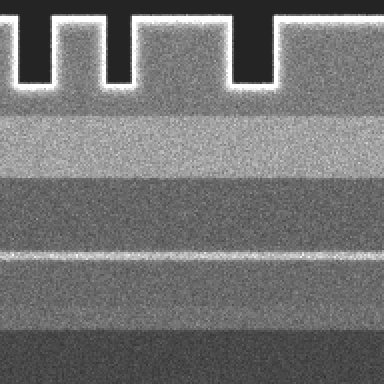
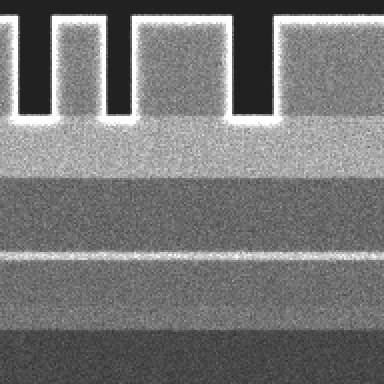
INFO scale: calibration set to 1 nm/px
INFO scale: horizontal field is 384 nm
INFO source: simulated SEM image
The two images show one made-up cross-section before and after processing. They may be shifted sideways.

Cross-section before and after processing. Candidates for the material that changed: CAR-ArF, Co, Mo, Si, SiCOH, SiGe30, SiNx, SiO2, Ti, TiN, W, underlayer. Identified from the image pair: underlayer (removed).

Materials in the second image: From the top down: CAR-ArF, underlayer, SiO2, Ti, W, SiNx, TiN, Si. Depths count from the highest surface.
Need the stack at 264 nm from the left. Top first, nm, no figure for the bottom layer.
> empty 100, SiO2 62, Ti 74, W 8, SiNx 46, TiN 24, Si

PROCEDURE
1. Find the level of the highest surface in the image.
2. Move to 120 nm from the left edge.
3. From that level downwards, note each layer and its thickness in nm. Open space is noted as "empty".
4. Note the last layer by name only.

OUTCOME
empty 100, SiO2 62, Ti 74, W 8, SiNx 46, TiN 24, Si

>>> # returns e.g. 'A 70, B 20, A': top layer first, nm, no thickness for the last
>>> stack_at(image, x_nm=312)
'CAR-ArF 68, underlayer 32, SiO2 62, Ti 74, W 8, SiNx 46, TiN 24, Si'